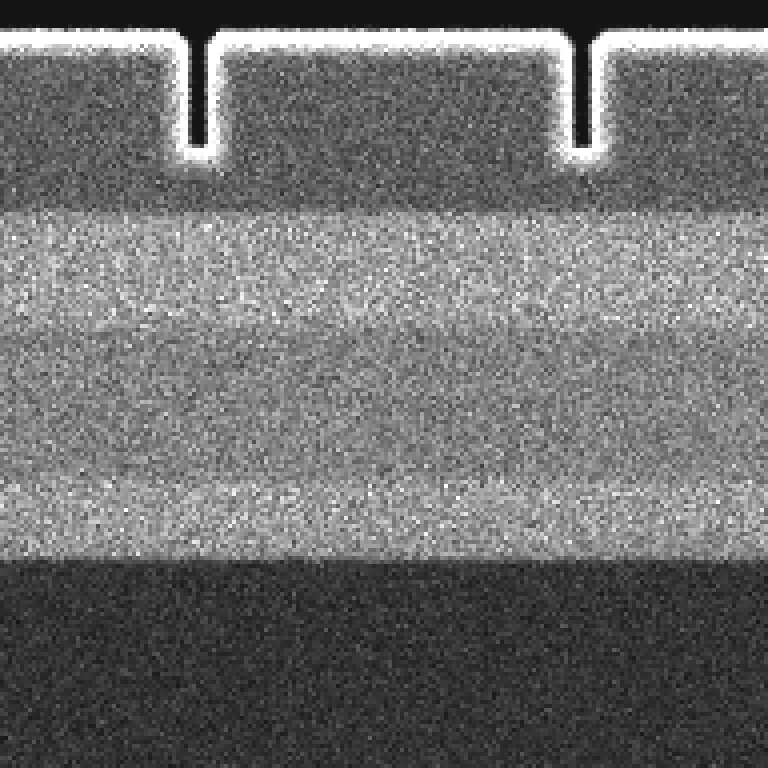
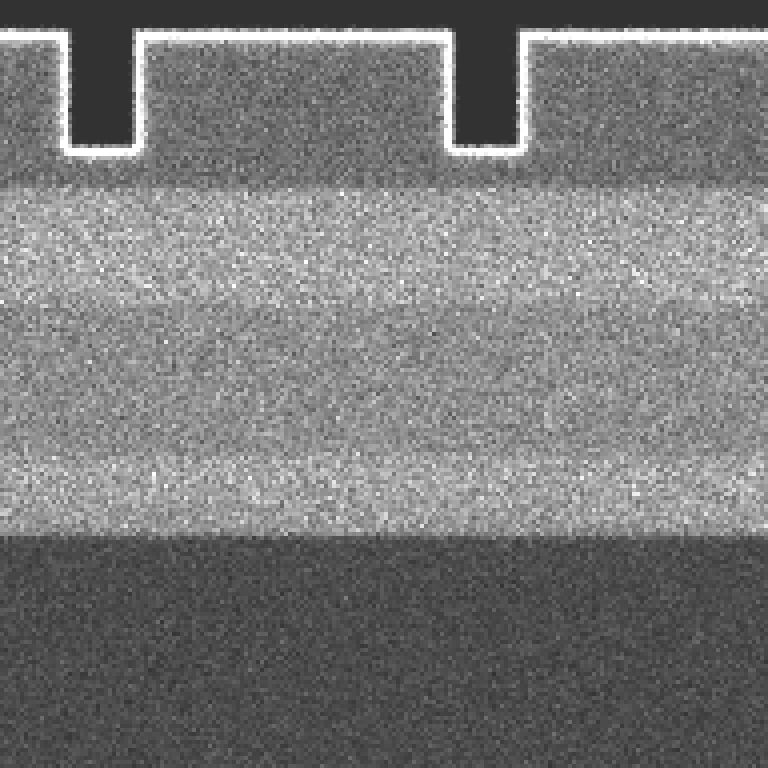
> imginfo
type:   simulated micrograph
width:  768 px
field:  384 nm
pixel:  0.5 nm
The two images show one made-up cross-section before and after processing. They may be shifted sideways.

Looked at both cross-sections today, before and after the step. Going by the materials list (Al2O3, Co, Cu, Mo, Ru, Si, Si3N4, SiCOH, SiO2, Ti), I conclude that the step removed Al2O3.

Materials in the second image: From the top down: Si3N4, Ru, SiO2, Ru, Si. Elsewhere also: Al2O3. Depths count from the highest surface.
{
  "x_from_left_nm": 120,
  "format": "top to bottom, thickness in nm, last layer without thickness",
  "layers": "Si3N4 78, Ru 58, SiO2 76, Ru 40, Si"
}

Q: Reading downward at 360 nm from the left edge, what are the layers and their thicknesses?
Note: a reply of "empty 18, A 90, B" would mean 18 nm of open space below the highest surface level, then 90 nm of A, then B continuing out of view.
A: Si3N4 78, Ru 58, SiO2 76, Ru 40, Si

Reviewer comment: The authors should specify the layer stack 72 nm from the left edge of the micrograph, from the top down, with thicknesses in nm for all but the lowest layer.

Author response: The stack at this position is Si3N4 78, Ru 58, SiO2 76, Ru 40, Si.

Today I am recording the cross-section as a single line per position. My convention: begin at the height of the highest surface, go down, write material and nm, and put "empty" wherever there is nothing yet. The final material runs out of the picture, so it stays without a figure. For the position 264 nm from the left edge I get Si3N4 78, Ru 58, SiO2 76, Ru 40, Si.